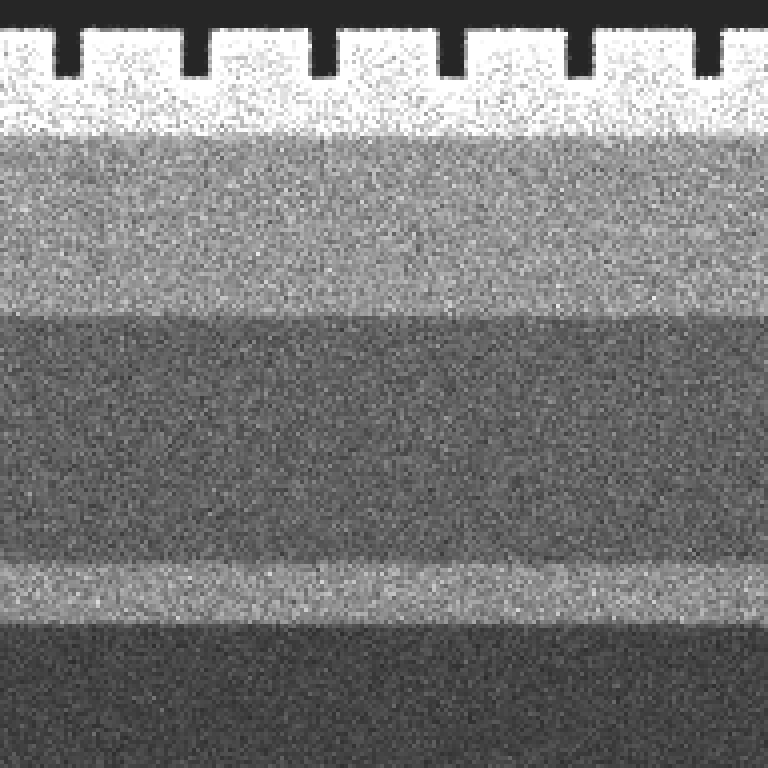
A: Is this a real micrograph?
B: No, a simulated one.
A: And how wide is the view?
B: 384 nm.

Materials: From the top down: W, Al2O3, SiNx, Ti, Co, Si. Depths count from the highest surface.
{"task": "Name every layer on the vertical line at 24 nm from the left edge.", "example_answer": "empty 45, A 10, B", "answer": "W 52, Al2O3 90, SiNx 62, Ti 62, Co 30, Si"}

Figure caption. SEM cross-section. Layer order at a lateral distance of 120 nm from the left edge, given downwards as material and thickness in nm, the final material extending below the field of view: W 52, Al2O3 90, SiNx 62, Ti 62, Co 30, Si